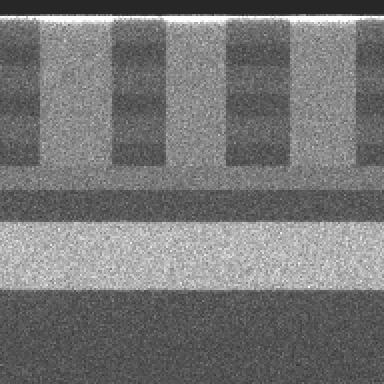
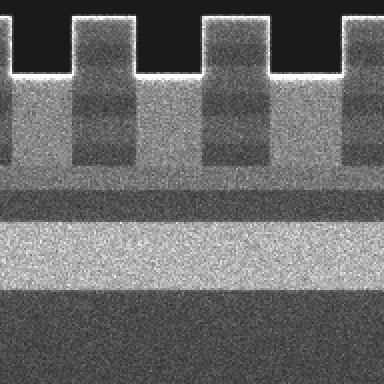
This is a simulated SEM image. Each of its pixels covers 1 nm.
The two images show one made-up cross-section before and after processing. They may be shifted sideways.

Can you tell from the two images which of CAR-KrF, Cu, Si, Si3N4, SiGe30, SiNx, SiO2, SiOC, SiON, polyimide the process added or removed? Yes, it removed Si3N4.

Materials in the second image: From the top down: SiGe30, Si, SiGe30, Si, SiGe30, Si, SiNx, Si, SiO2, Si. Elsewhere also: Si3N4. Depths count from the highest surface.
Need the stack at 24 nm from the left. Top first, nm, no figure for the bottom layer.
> empty 58, Si3N4 92, SiNx 24, Si 32, SiO2 68, Si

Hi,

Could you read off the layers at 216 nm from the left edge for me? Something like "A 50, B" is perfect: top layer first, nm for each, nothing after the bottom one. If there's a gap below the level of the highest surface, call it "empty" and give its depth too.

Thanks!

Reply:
SiGe30 28, Si 22, SiGe30 28, Si 22, SiGe30 28, Si 22, SiNx 24, Si 32, SiO2 68, Si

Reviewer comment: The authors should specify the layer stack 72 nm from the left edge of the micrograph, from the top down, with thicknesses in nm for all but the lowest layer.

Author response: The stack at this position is SiGe30 28, Si 22, SiGe30 28, Si 22, SiGe30 28, Si 22, SiNx 24, Si 32, SiO2 68, Si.